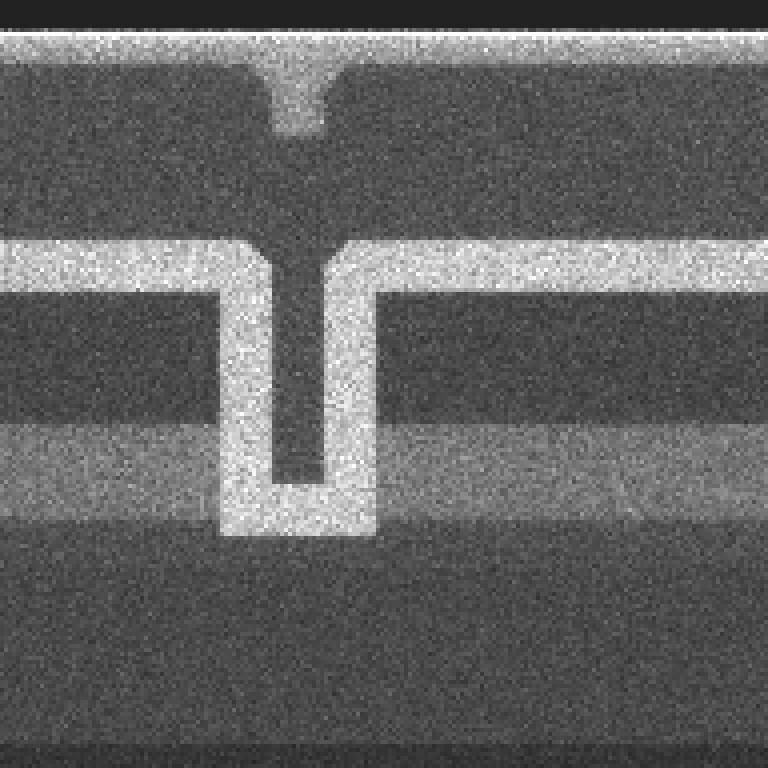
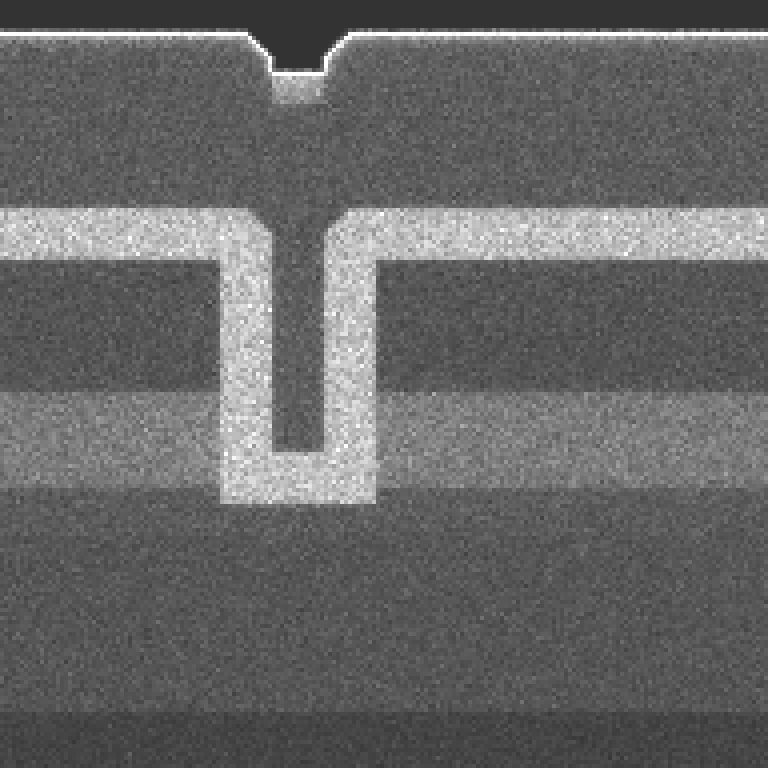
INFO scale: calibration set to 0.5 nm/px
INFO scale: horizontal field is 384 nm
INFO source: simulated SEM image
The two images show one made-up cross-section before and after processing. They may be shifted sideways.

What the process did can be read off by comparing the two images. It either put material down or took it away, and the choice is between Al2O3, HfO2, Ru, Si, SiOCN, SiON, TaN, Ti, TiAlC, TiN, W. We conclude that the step removed W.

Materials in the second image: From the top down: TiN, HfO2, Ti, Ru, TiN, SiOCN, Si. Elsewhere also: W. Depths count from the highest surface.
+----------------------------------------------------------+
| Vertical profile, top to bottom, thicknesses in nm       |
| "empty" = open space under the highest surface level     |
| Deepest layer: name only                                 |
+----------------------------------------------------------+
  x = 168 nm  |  empty 6, TiN 88, HfO2 142, TiN 16, SiOCN 88, Si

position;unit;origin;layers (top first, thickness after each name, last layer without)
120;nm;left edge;TiN 88, HfO2 148, TiN 16, SiOCN 88, Si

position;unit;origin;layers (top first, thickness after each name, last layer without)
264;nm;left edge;TiN 88, HfO2 26, Ti 66, Ru 48, TiN 24, SiOCN 88, Si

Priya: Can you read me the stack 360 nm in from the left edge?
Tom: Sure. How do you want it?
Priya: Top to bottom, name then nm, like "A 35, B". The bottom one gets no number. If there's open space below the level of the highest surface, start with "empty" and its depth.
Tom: TiN 88, HfO2 26, Ti 66, Ru 48, TiN 24, SiOCN 88, Si